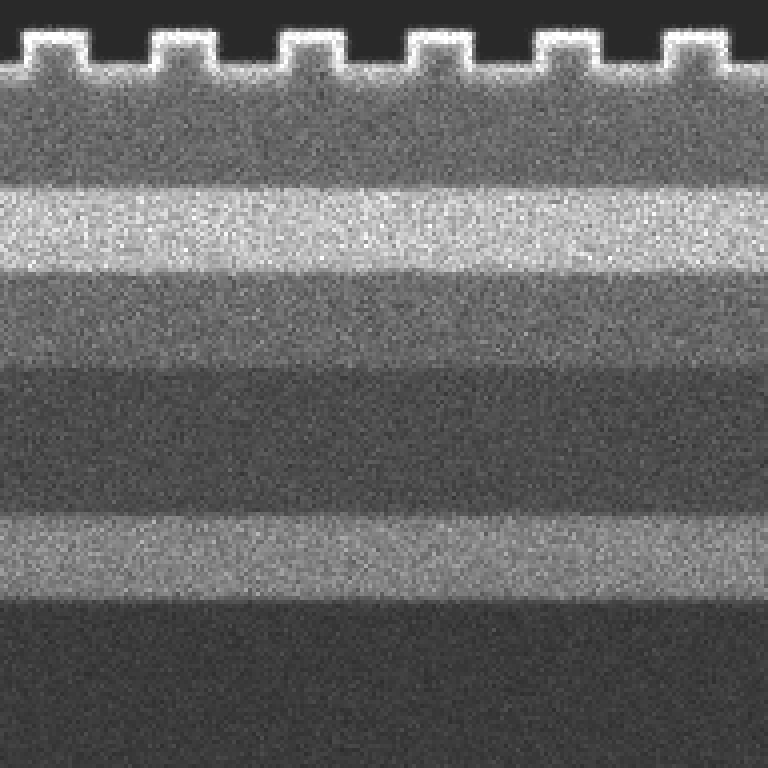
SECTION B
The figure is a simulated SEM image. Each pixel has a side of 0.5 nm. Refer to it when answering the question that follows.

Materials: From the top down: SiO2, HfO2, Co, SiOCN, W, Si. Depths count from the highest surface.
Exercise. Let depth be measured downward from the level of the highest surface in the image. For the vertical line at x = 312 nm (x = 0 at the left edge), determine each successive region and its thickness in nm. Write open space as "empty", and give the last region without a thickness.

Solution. empty 16, SiO2 62, HfO2 42, Co 48, SiOCN 74, W 42, Si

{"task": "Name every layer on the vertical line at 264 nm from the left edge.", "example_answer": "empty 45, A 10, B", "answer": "empty 16, SiO2 62, HfO2 42, Co 48, SiOCN 74, W 42, Si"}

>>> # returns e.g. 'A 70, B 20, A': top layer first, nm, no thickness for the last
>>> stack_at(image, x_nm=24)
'SiO2 78, HfO2 42, Co 48, SiOCN 74, W 42, Si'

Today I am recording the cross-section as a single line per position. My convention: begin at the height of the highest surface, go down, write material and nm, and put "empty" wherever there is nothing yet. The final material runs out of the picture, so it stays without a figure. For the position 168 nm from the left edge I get SiO2 78, HfO2 42, Co 48, SiOCN 74, W 42, Si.